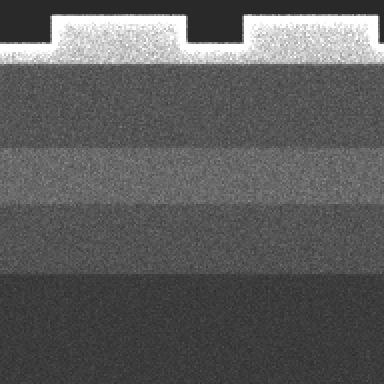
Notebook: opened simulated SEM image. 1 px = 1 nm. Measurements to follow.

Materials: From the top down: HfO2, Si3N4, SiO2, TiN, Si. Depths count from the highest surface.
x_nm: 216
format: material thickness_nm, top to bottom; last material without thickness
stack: empty 28, HfO2 20, Si3N4 84, SiO2 56, TiN 70, Si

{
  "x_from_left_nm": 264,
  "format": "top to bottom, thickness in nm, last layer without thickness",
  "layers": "HfO2 48, Si3N4 84, SiO2 56, TiN 70, Si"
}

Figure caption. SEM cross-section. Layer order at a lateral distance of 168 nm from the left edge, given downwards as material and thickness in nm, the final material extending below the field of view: HfO2 48, Si3N4 84, SiO2 56, TiN 70, Si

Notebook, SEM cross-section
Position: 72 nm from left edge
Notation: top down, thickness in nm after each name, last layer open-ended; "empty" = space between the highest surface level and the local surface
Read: HfO2 48, Si3N4 84, SiO2 56, TiN 70, Si